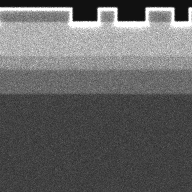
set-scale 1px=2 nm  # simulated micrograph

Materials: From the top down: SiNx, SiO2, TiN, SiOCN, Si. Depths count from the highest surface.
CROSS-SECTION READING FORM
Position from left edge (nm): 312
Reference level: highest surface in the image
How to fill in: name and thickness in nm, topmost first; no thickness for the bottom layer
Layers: SiNx 28, SiO2 68, TiN 28, SiOCN 48, Si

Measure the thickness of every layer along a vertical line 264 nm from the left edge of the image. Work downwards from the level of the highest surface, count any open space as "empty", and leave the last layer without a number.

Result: empty 28, SiO2 68, TiN 28, SiOCN 48, Si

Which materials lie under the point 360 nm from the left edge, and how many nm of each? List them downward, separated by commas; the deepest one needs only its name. empty 28, SiO2 68, TiN 28, SiOCN 48, Si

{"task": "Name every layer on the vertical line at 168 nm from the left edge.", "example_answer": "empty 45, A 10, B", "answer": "empty 28, SiO2 68, TiN 28, SiOCN 48, Si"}